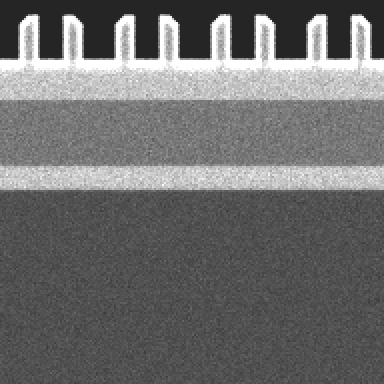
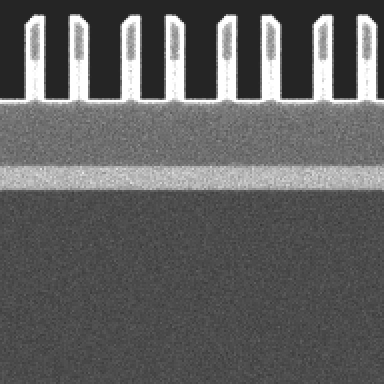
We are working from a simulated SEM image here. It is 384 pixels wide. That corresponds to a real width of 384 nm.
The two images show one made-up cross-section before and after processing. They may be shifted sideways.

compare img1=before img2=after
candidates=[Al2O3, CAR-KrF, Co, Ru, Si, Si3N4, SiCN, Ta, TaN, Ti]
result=removed:Al2O3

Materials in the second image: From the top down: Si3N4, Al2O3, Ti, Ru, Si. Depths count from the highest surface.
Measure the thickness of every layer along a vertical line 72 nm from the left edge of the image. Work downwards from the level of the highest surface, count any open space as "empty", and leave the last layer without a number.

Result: Si3N4 44, Al2O3 40, Ti 66, Ru 24, Si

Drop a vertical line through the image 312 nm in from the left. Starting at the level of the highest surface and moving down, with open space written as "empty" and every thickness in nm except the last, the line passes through empty 84, Ti 66, Ru 24, Si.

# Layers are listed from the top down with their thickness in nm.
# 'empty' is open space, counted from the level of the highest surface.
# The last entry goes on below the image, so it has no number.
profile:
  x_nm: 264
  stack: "Si3N4 44, Al2O3 40, Ti 66, Ru 24, Si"